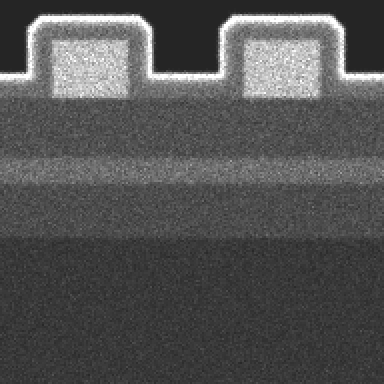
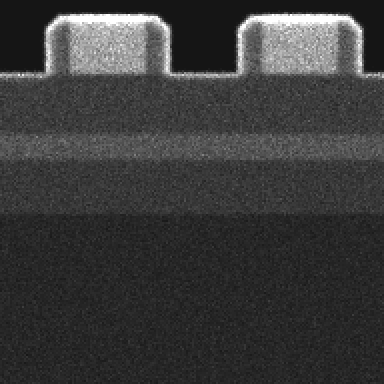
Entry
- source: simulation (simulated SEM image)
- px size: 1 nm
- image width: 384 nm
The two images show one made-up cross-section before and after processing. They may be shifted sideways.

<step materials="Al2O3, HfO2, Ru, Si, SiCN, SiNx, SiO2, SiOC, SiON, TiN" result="removed SiO2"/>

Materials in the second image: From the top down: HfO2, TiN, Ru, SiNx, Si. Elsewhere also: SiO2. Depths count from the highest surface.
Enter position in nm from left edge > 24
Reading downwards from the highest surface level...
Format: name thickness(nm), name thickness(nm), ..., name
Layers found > empty 58, TiN 60, Ru 26, SiNx 54, Si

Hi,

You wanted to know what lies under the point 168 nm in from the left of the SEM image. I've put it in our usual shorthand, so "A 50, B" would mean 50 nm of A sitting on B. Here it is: empty 12, SiO2 46, TiN 60, Ru 26, SiNx 54, Si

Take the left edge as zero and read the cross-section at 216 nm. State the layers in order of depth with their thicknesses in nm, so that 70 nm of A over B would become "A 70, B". empty 58, TiN 60, Ru 26, SiNx 54, Si